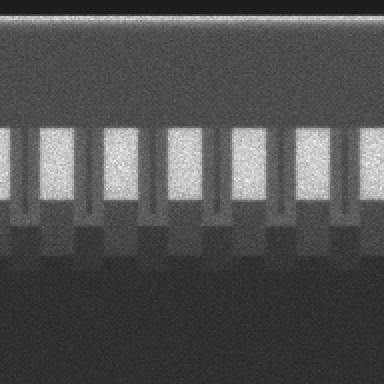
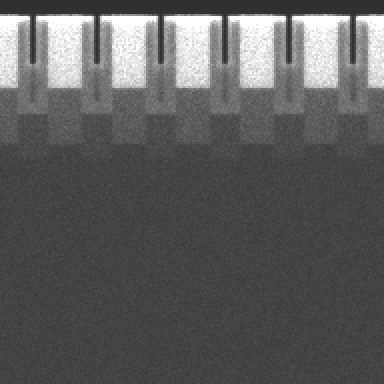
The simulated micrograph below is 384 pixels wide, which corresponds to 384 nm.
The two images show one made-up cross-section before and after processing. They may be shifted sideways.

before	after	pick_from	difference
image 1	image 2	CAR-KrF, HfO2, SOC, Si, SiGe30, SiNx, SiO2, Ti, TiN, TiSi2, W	SOC removed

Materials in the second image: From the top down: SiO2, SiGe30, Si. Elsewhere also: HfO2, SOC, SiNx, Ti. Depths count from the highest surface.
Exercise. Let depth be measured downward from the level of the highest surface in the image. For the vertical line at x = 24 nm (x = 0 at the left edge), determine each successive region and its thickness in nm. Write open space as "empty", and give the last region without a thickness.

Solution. SiO2 98, SiGe30 44, Si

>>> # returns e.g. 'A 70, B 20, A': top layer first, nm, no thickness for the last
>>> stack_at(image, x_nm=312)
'HfO2 72, Ti 56, Si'